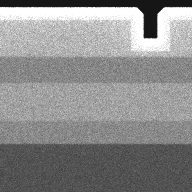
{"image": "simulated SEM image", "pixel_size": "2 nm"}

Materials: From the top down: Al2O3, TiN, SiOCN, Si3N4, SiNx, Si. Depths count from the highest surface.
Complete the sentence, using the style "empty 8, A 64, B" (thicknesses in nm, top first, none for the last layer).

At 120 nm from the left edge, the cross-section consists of Al2O3 24, TiN 74, SiOCN 52, Si3N4 76, SiNx 46, Si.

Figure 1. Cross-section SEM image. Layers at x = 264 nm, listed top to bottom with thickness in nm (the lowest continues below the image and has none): Al2O3 86, TiN 12, SiOCN 52, Si3N4 76, SiNx 46, Si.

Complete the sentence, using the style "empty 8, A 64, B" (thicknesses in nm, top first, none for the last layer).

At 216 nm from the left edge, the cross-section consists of Al2O3 24, TiN 74, SiOCN 52, Si3N4 76, SiNx 46, Si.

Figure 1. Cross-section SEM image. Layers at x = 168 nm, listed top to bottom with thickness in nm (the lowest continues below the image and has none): Al2O3 24, TiN 74, SiOCN 52, Si3N4 76, SiNx 46, Si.